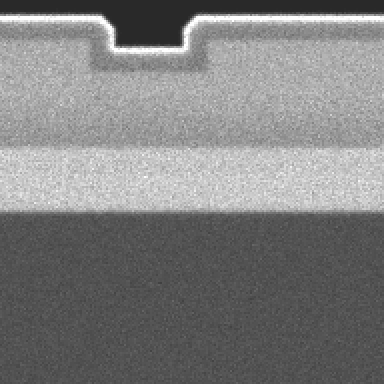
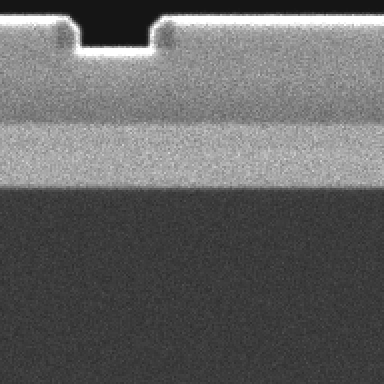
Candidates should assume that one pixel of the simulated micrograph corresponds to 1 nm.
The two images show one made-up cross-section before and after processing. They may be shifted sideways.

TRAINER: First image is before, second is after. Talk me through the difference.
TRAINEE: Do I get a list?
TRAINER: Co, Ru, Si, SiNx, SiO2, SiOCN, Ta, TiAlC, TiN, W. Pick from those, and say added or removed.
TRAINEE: removed: SiNx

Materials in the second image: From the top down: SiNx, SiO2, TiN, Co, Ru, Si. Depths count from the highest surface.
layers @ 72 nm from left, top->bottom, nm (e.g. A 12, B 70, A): empty 6, SiNx 26, SiO2 22, TiN 54, Co 26, Ru 38, Si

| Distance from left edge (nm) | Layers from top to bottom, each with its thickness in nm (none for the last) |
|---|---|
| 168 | SiNx 32, SiO2 22, TiN 54, Co 26, Ru 38, Si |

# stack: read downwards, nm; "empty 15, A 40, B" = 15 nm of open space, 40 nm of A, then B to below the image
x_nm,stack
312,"SiO2 54, TiN 54, Co 26, Ru 38, Si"